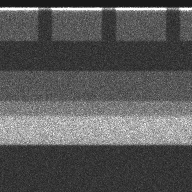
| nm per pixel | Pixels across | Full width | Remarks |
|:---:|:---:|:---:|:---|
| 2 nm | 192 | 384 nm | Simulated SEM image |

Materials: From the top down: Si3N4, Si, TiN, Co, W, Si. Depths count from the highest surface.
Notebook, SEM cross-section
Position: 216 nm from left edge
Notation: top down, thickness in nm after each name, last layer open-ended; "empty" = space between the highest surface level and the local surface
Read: Si 126, TiN 60, Co 30, W 58, Si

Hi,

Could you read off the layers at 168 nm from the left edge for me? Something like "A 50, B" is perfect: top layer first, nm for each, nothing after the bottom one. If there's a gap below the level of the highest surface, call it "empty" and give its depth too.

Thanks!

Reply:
Si3N4 66, Si 60, TiN 60, Co 30, W 58, Si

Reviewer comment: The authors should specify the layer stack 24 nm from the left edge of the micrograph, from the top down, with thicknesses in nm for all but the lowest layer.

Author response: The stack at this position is Si3N4 66, Si 60, TiN 60, Co 30, W 58, Si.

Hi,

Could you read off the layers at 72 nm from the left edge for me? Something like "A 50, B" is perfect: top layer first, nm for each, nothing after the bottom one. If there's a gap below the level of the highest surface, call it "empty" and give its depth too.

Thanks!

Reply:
Si3N4 66, Si 60, TiN 60, Co 30, W 58, Si